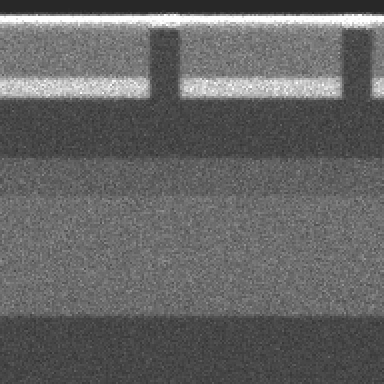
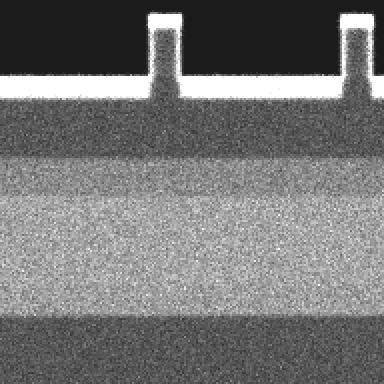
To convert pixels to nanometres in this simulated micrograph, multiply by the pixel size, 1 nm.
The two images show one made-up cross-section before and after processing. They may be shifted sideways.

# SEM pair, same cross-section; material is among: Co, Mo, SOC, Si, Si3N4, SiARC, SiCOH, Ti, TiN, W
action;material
removed;SOC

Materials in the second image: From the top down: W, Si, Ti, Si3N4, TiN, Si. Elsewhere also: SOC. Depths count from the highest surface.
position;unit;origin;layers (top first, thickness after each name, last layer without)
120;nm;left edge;empty 62, W 20, Si 60, Ti 38, Si3N4 88, TiN 32, Si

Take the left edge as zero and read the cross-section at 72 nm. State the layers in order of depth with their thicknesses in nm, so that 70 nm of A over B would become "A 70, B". empty 62, W 20, Si 60, Ti 38, Si3N4 88, TiN 32, Si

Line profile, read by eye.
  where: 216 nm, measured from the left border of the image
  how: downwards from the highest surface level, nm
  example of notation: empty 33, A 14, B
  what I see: empty 62, W 20, Si 60, Ti 38, Si3N4 88, TiN 32, Si